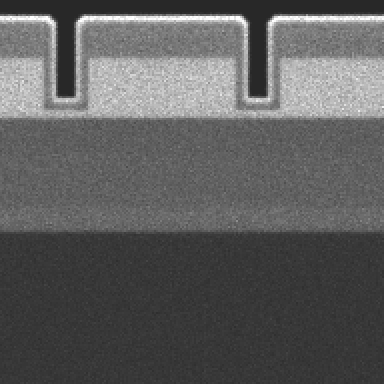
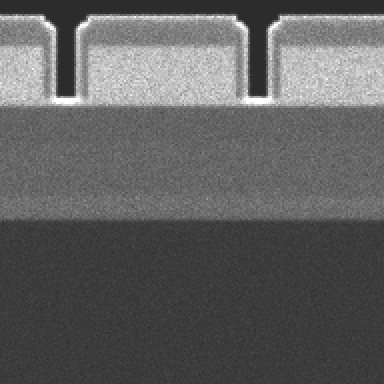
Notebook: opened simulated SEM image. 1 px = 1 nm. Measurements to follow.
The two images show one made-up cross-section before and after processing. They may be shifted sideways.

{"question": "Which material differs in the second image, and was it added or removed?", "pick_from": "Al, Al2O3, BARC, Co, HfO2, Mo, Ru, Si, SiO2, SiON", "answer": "Al2O3, removed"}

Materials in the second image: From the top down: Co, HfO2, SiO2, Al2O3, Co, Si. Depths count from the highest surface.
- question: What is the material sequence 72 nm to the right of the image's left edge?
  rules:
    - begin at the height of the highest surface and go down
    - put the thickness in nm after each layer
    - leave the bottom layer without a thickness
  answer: empty 82, HfO2 8, SiO2 36, Al2O3 54, Co 24, Si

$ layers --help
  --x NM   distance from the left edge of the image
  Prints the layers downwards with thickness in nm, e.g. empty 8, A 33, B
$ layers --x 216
Co 30, HfO2 60, SiO2 36, Al2O3 54, Co 24, Si